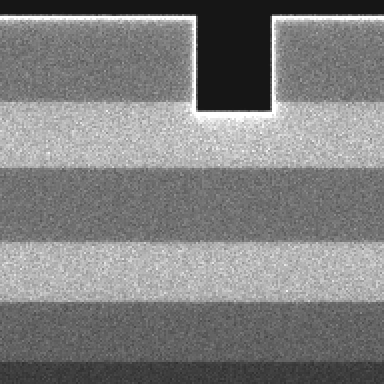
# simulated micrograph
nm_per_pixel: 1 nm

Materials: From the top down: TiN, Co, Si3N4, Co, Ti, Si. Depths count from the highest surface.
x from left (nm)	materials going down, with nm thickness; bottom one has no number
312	TiN 86, Co 66, Si3N4 74, Co 60, Ti 60, Si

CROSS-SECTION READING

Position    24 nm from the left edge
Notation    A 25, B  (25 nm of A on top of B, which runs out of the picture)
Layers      TiN 86, Co 66, Si3N4 74, Co 60, Ti 60, Si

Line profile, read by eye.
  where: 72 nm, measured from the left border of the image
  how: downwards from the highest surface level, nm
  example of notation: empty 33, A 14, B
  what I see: TiN 86, Co 66, Si3N4 74, Co 60, Ti 60, Si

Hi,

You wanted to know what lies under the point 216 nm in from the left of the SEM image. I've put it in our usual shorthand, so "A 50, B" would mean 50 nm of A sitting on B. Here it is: empty 96, Co 56, Si3N4 74, Co 60, Ti 60, Si